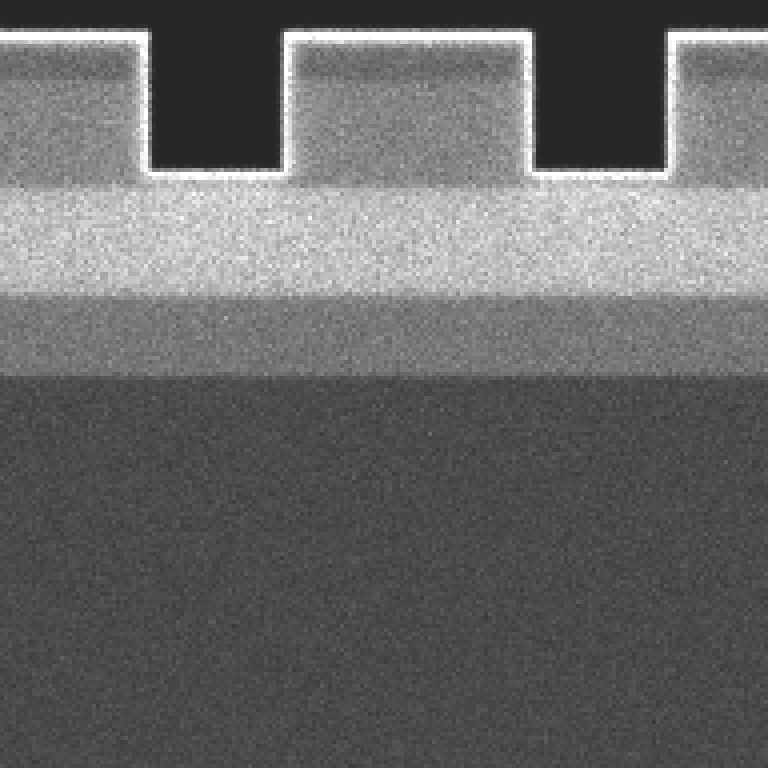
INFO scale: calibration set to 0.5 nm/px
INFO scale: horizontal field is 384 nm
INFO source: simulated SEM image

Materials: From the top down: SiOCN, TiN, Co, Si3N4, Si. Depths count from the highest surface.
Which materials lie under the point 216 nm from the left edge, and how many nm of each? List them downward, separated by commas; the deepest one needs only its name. SiOCN 24, TiN 54, Co 54, Si3N4 40, Si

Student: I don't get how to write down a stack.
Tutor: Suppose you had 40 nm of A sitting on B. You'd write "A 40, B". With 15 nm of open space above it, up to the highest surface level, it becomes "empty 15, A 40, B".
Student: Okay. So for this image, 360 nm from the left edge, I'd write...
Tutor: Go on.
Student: SiOCN 24, TiN 54, Co 54, Si3N4 40, Si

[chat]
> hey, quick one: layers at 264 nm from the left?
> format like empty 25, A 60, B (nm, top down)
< SiOCN 24, TiN 54, Co 54, Si3N4 40, Si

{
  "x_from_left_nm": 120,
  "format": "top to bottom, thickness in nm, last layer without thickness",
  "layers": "empty 70, TiN 8, Co 54, Si3N4 40, Si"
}